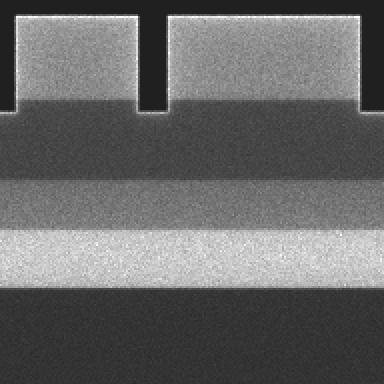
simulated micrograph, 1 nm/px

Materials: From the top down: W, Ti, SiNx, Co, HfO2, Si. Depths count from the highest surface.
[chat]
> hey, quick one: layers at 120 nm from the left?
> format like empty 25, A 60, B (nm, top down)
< W 84, Ti 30, SiNx 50, Co 50, HfO2 58, Si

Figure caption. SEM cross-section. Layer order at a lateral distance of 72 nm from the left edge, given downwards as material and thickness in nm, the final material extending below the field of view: W 84, Ti 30, SiNx 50, Co 50, HfO2 58, Si